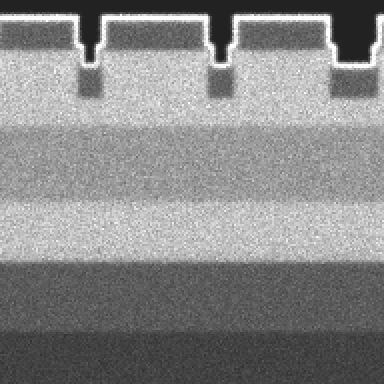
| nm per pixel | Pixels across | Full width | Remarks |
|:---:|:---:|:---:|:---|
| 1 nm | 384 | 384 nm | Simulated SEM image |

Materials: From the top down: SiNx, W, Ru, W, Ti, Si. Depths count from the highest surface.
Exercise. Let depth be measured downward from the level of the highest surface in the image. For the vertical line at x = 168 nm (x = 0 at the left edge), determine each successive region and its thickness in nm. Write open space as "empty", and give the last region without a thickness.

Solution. SiNx 34, W 76, Ru 76, W 60, Ti 70, Si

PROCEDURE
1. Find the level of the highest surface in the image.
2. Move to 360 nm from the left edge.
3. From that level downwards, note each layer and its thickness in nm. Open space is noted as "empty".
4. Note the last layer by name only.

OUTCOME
empty 48, SiNx 34, W 28, Ru 76, W 60, Ti 70, Si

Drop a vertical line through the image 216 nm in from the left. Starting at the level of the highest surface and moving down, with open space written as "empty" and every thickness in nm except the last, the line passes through empty 48, SiNx 34, W 28, Ru 76, W 60, Ti 70, Si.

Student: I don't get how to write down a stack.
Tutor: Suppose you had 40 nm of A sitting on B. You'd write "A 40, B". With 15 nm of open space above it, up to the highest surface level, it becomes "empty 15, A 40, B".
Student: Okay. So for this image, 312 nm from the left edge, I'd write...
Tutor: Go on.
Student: SiNx 34, W 76, Ru 76, W 60, Ti 70, Si